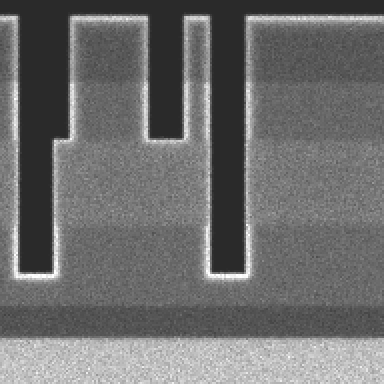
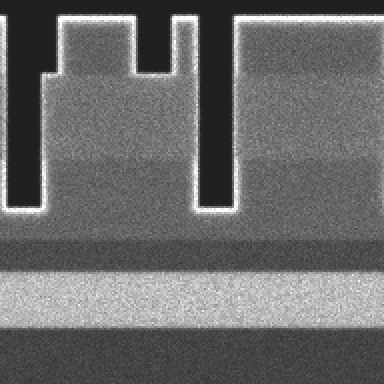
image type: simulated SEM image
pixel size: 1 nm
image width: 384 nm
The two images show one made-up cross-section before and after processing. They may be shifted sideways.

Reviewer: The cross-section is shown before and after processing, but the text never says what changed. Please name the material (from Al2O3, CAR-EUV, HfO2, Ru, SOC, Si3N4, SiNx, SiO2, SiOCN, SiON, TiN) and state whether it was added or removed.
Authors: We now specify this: SOC, removed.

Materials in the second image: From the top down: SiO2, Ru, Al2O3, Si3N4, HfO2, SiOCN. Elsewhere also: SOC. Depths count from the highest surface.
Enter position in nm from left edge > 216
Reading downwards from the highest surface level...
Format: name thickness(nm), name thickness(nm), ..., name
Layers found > empty 192, Al2O3 32, Si3N4 32, HfO2 56, SiOCN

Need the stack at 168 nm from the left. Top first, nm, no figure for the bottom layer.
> empty 58, Ru 86, Al2O3 80, Si3N4 32, HfO2 56, SiOCN